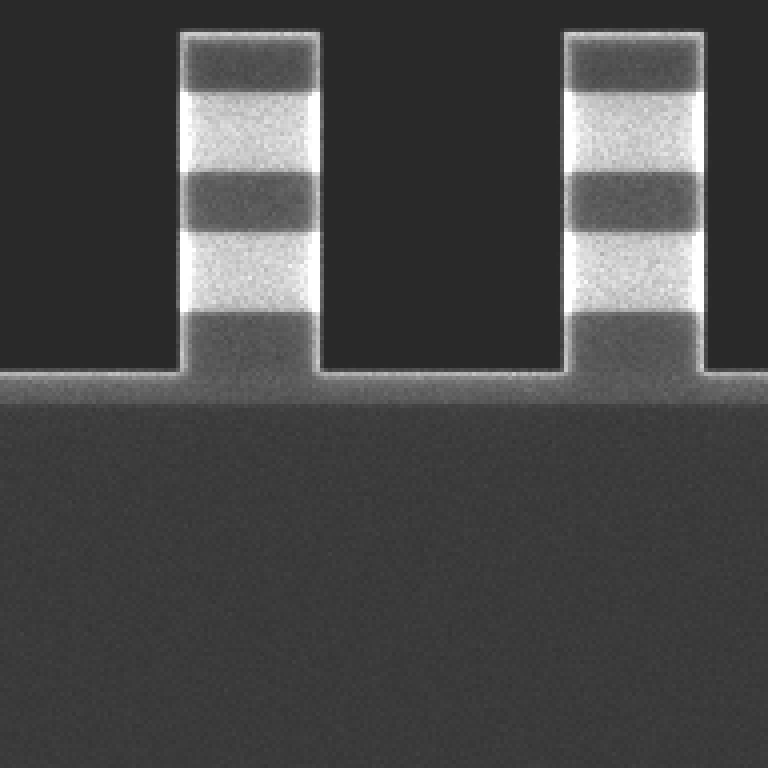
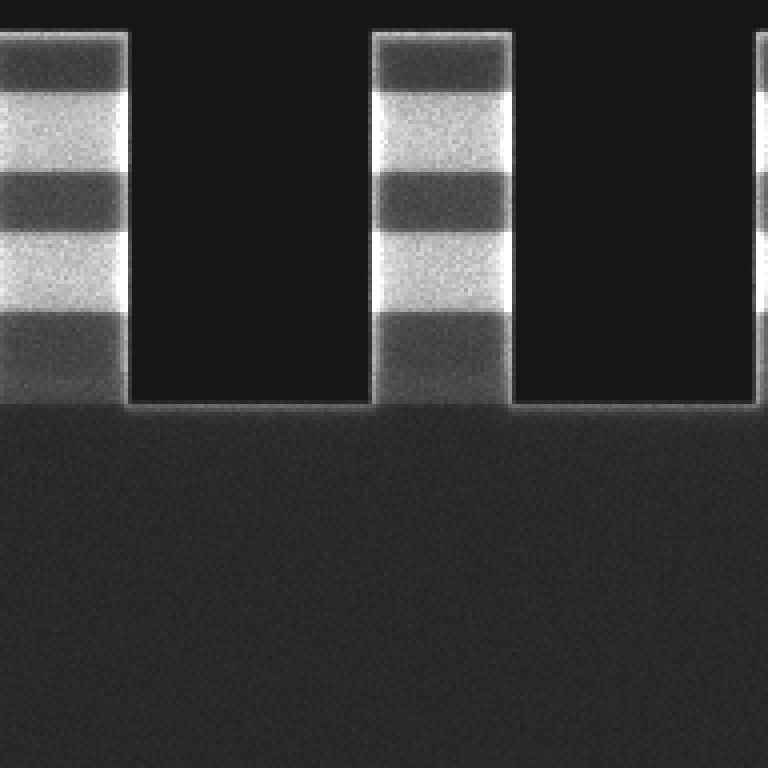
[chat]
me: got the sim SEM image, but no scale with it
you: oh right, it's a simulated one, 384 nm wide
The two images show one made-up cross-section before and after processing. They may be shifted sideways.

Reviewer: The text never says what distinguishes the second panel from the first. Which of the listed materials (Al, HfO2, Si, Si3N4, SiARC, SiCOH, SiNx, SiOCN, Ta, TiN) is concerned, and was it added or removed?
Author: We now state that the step removed TiN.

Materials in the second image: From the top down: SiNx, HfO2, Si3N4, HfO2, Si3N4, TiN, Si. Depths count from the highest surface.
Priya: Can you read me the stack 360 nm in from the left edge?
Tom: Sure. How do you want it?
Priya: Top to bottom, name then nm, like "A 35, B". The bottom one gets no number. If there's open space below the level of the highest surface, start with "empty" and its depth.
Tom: empty 186, Si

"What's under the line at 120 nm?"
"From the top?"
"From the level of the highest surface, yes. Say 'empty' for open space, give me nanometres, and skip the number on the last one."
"empty 186, Si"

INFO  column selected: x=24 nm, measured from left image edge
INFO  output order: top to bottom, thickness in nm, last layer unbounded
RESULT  SiNx 30, HfO2 40, Si3N4 30, HfO2 40, Si3N4 30, TiN 16, Si